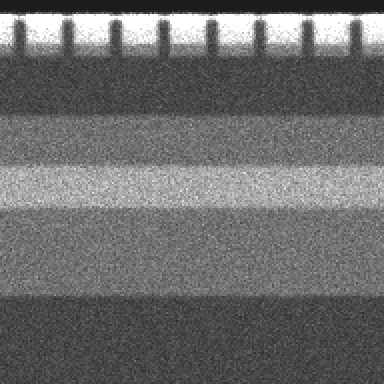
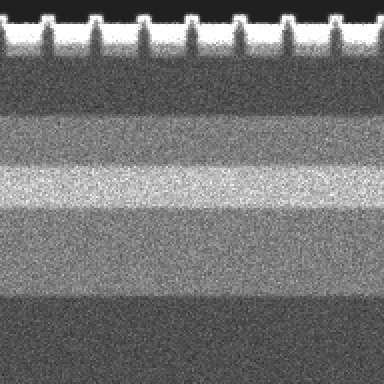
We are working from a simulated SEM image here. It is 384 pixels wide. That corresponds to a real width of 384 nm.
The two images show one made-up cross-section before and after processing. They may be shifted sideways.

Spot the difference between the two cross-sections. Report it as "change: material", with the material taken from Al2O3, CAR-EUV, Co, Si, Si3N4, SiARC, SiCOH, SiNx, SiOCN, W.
removed: W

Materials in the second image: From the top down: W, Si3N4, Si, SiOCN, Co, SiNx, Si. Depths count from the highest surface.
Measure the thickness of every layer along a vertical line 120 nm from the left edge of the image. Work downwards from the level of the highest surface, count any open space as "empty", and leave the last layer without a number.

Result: empty 10, W 18, Si3N4 12, Si 60, SiOCN 50, Co 42, SiNx 88, Si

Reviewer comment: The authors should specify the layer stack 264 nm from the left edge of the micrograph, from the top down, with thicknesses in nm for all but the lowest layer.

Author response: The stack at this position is empty 10, W 18, Si3N4 12, Si 60, SiOCN 50, Co 42, SiNx 88, Si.